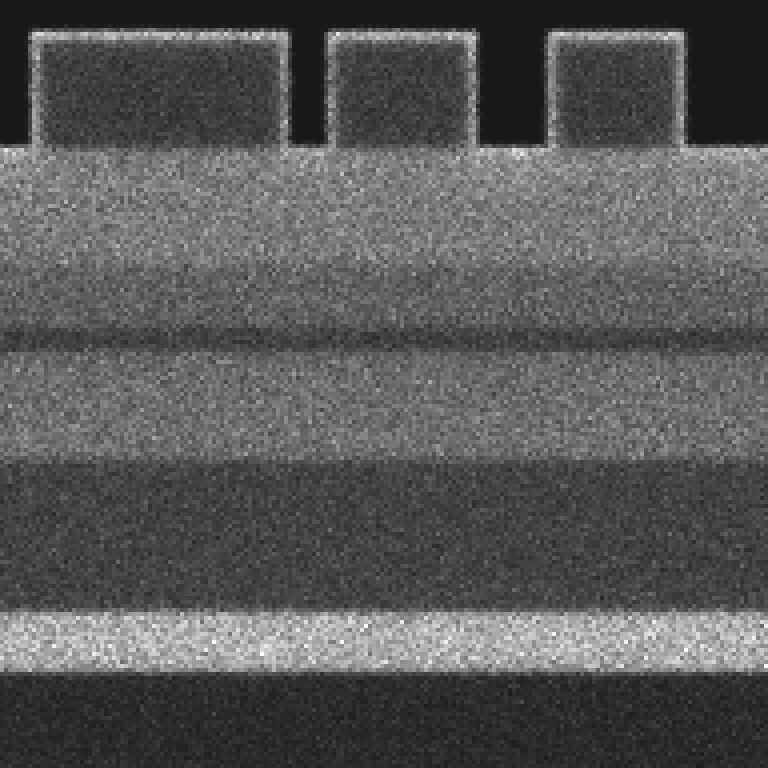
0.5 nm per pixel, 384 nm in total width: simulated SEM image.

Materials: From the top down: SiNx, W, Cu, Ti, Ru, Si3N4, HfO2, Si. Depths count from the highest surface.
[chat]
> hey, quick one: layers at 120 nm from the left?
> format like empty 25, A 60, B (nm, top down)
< SiNx 58, W 58, Cu 32, Ti 12, Ru 54, Si3N4 76, HfO2 30, Si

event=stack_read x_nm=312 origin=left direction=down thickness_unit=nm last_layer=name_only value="SiNx 58, W 58, Cu 32, Ti 12, Ru 54, Si3N4 76, HfO2 30, Si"